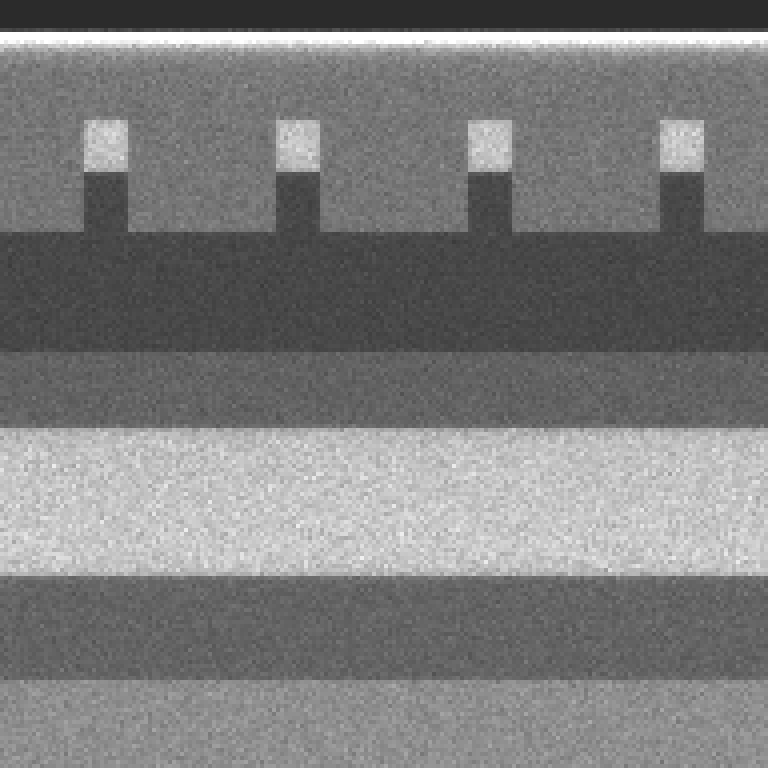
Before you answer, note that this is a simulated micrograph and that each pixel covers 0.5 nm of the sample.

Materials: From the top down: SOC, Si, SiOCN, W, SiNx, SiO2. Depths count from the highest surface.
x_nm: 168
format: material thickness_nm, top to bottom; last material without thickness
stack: SOC 100, Si 60, SiOCN 38, W 74, SiNx 52, SiO2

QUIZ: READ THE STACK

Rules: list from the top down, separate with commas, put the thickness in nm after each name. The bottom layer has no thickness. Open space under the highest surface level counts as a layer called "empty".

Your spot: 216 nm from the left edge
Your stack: SOC 100, Si 60, SiOCN 38, W 74, SiNx 52, SiO2